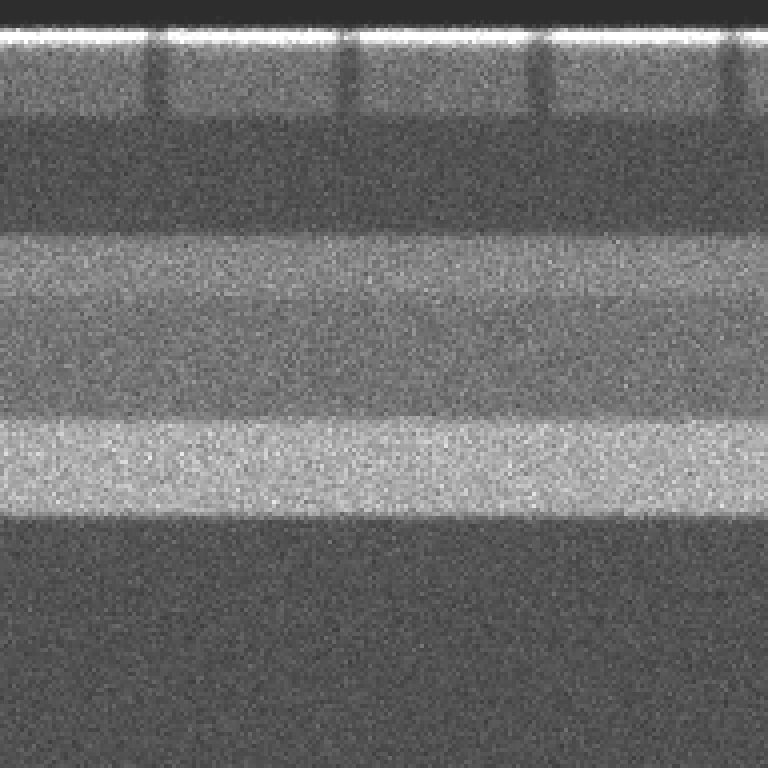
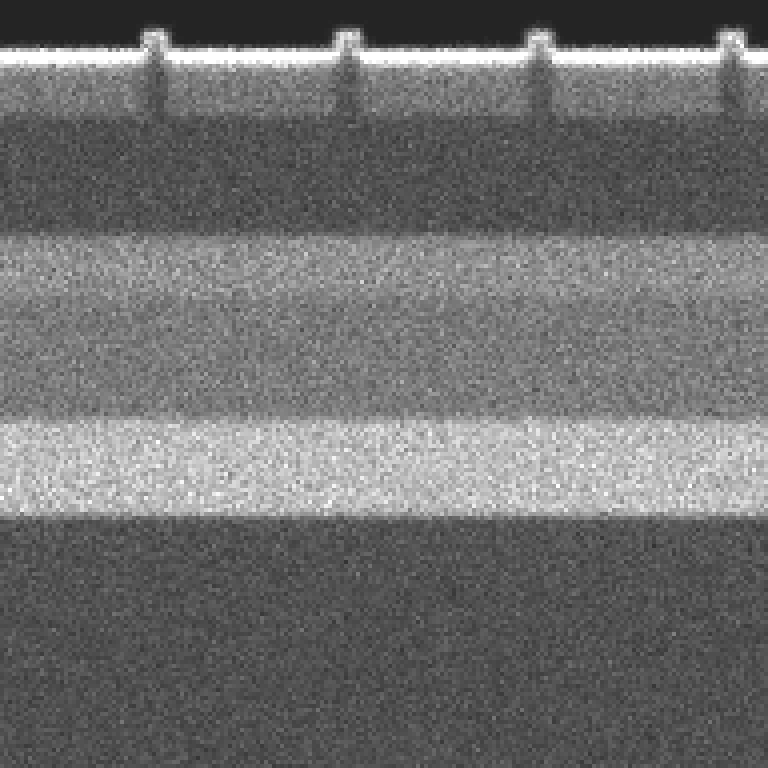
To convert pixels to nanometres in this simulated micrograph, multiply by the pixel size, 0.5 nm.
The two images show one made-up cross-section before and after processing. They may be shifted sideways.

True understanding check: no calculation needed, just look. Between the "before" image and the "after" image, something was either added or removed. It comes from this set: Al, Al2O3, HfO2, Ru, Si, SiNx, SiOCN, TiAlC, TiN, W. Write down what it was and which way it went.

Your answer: SiOCN (removed)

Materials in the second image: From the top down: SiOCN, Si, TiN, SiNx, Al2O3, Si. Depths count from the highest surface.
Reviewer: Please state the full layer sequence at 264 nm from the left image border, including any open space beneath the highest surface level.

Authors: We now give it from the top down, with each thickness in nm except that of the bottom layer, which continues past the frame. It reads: Si 102, TiN 30, SiNx 62, Al2O3 48, Si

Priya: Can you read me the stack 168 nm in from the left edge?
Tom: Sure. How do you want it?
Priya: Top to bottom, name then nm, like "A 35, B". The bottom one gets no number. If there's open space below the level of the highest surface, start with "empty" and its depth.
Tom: Si 102, TiN 30, SiNx 62, Al2O3 48, Si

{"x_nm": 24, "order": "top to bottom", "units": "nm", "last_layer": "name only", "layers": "empty 10, SiOCN 32, Si 60, TiN 30, SiNx 62, Al2O3 48, Si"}